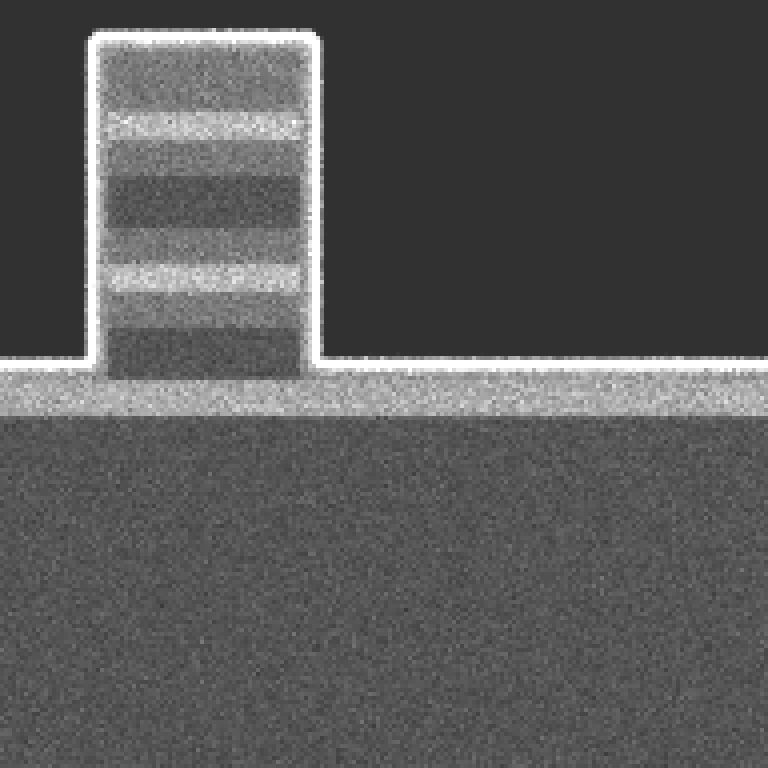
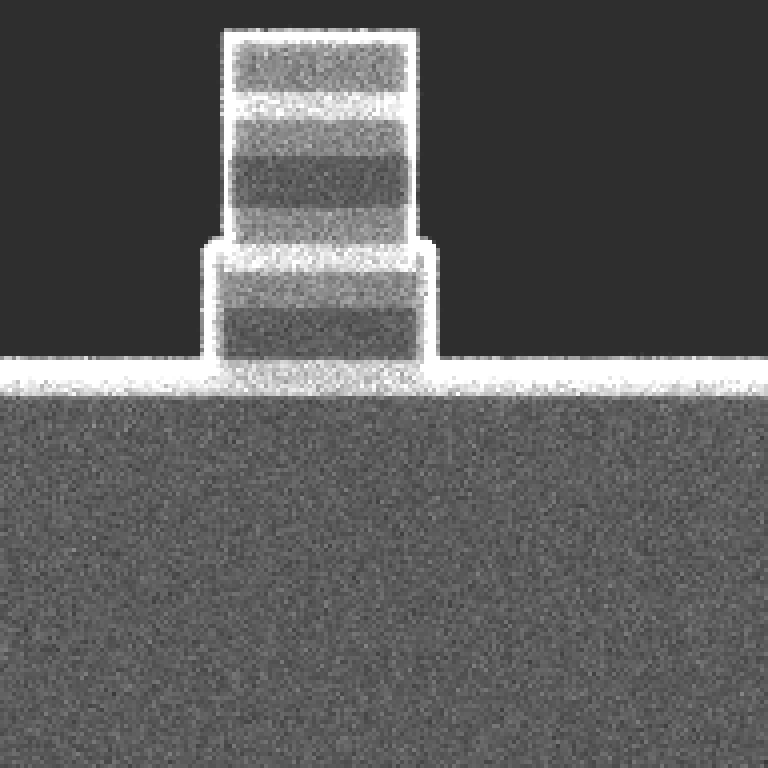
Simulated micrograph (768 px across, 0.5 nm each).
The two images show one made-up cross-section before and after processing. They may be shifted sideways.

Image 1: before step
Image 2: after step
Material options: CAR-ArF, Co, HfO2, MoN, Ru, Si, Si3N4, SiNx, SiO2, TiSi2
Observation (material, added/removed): Si3N4, removed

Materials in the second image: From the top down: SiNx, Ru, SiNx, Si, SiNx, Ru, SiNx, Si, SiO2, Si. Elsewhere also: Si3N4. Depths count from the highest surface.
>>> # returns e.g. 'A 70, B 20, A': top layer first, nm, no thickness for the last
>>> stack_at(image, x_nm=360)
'empty 164, SiO2 18, Si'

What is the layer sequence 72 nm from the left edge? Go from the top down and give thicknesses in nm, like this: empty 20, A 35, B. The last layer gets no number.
empty 164, SiO2 18, Si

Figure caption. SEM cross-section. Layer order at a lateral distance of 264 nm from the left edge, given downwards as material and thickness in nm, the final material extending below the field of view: empty 164, SiO2 18, Si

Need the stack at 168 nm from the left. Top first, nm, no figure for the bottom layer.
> SiNx 30, Ru 14, SiNx 18, Si 26, SiNx 18, Ru 14, SiNx 18, Si 26, SiO2 18, Si